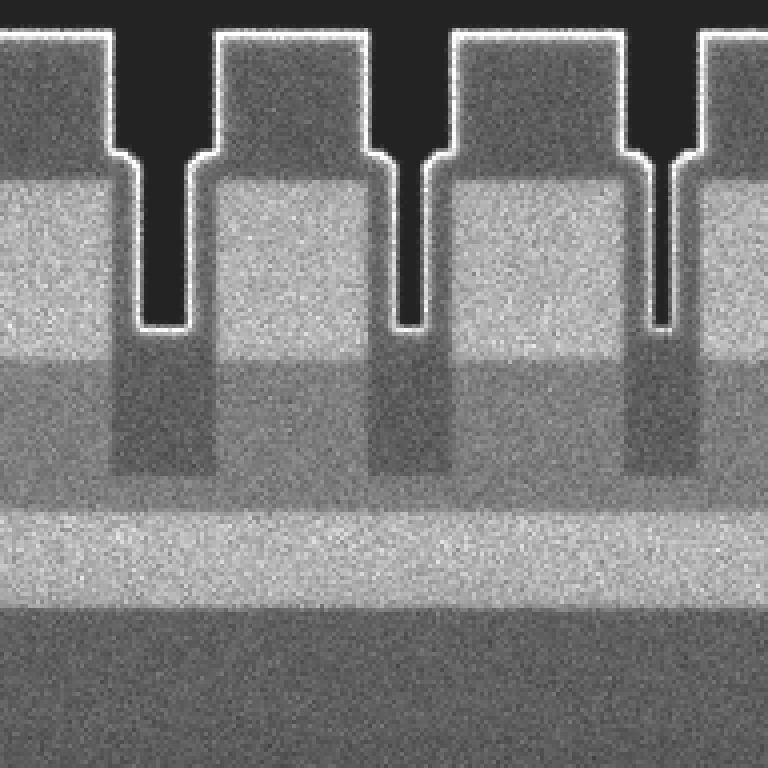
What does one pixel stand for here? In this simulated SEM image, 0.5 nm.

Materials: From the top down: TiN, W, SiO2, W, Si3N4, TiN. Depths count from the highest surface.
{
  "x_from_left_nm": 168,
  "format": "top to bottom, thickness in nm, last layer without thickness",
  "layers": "TiN 74, W 90, SiO2 76, W 48, Si3N4 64, TiN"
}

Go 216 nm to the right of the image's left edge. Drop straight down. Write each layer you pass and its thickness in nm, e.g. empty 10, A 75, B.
empty 62, TiN 160, SiO2 18, W 48, Si3N4 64, TiN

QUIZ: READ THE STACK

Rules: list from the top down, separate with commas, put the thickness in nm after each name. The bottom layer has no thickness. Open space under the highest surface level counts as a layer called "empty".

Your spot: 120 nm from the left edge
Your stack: TiN 74, W 90, SiO2 76, W 48, Si3N4 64, TiN